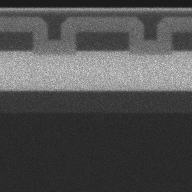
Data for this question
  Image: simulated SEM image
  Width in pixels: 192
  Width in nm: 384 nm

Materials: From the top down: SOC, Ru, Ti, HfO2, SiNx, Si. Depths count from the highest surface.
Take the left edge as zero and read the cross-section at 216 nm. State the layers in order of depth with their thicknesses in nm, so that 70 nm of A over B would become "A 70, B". SOC 18, Ru 30, Ti 38, HfO2 80, SiNx 44, Si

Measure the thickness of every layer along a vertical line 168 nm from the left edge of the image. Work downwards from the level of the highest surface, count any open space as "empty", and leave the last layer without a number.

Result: SOC 18, Ru 30, Ti 38, HfO2 80, SiNx 44, Si